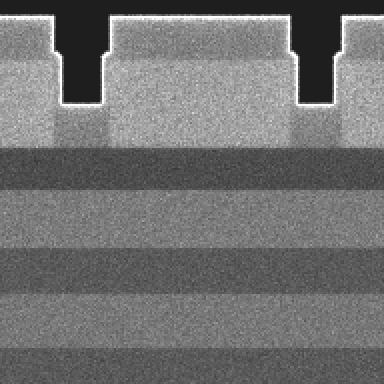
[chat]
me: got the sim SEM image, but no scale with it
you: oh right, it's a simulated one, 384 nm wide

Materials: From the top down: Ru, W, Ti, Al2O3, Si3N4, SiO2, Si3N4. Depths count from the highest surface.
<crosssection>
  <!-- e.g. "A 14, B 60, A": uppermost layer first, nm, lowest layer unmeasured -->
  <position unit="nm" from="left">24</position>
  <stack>Ru 44, W 88, Ti 42, Al2O3 58, Si3N4 46, SiO2 54, Si3N4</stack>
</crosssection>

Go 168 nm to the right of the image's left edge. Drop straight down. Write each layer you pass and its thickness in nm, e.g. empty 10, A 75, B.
Ru 44, W 88, Ti 42, Al2O3 58, Si3N4 46, SiO2 54, Si3N4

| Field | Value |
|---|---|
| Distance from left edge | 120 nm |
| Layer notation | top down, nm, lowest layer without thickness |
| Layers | Ru 44, W 88, Ti 42, Al2O3 58, Si3N4 46, SiO2 54, Si3N4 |